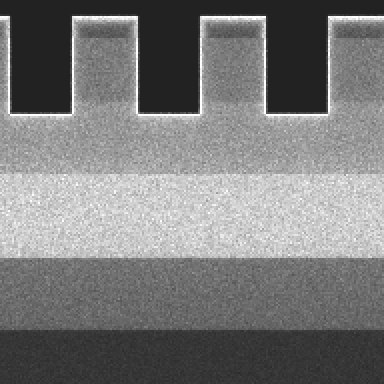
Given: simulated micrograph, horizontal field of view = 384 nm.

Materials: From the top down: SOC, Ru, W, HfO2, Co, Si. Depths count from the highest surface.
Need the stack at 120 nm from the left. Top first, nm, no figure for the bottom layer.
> SOC 22, Ru 64, W 72, HfO2 84, Co 72, Si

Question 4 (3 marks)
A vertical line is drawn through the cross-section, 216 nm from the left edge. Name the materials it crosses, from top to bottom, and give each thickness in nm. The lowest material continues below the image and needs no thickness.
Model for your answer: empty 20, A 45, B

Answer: SOC 22, Ru 64, W 72, HfO2 84, Co 72, Si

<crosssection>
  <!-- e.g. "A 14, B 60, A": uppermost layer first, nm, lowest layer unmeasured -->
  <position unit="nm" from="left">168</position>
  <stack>empty 98, W 60, HfO2 84, Co 72, Si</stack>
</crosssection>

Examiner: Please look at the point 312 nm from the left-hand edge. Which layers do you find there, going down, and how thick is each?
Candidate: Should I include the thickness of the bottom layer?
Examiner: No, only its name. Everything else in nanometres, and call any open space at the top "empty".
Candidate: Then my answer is empty 98, W 60, HfO2 84, Co 72, Si